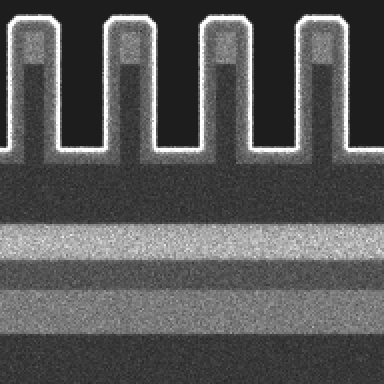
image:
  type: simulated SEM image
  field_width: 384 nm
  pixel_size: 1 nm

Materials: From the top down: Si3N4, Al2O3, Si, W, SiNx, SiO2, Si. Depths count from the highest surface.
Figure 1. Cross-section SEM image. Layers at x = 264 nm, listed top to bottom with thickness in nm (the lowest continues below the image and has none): empty 132, Si3N4 16, Si 60, W 36, SiNx 30, SiO2 44, Si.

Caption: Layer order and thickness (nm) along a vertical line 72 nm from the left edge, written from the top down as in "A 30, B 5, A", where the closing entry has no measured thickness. empty 132, Si3N4 16, Si 60, W 36, SiNx 30, SiO2 44, Si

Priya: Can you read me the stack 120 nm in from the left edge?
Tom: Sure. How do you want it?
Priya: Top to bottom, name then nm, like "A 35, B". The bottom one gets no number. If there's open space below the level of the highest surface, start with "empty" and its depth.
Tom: Si3N4 16, Al2O3 32, Si 160, W 36, SiNx 30, SiO2 44, Si